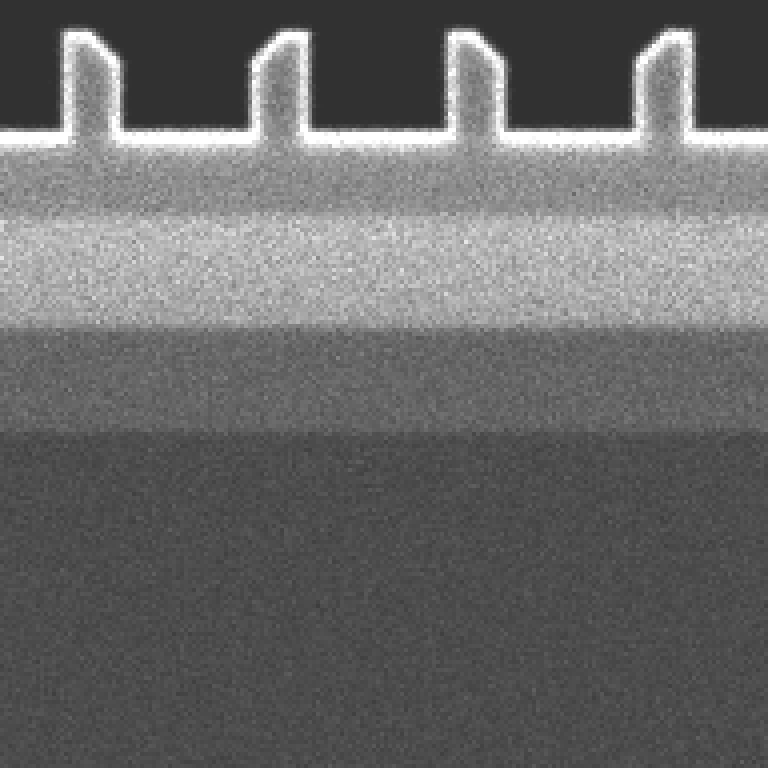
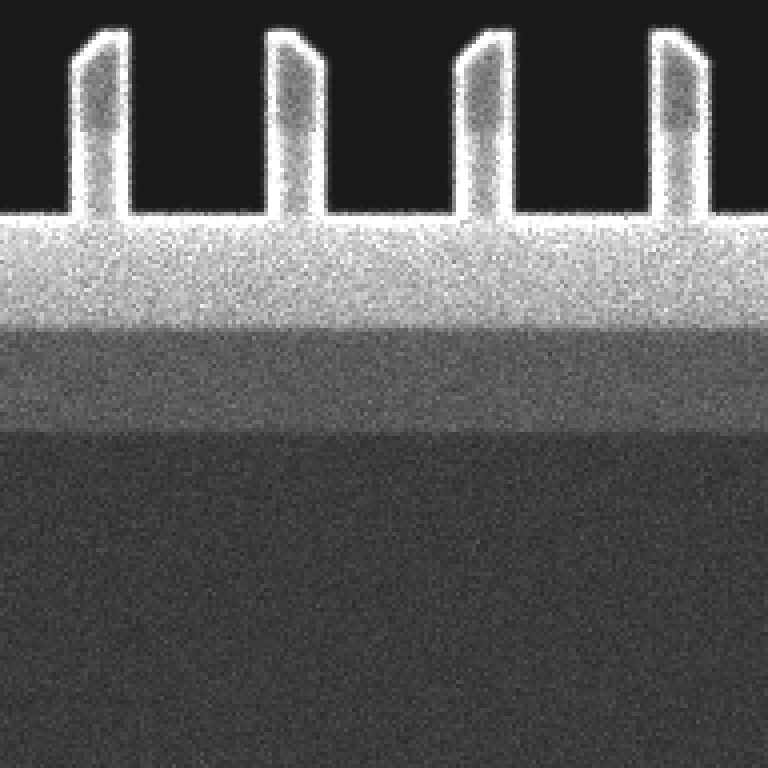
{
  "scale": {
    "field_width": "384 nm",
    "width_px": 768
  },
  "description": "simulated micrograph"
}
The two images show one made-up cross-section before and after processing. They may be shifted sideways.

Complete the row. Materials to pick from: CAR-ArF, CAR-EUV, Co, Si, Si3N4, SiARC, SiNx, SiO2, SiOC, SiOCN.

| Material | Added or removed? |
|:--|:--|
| SiO2 | removed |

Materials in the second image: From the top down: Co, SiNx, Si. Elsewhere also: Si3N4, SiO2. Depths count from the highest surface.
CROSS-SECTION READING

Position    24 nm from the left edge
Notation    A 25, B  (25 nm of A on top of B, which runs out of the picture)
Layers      empty 92, Co 56, SiNx 52, Si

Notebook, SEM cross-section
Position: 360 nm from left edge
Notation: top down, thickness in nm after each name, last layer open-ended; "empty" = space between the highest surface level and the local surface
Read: empty 92, Co 56, SiNx 52, Si